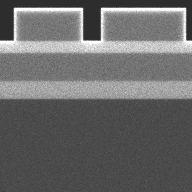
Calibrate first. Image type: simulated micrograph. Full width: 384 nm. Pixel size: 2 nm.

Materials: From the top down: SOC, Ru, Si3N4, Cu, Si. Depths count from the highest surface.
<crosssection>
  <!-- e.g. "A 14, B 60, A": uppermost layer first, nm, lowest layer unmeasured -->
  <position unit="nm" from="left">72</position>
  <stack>SOC 66, Ru 24, Si3N4 56, Cu 36, Si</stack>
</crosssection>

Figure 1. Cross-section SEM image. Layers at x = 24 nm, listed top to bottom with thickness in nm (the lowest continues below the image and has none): empty 66, Ru 24, Si3N4 56, Cu 36, Si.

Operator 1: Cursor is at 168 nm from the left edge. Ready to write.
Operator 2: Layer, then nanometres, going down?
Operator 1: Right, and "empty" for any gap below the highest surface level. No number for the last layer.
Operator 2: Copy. empty 66, Ru 24, Si3N4 56, Cu 36, Si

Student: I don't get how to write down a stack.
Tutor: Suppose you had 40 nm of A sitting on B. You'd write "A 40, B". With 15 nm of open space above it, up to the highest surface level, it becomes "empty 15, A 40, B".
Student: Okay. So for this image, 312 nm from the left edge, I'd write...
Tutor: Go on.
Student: SOC 66, Ru 24, Si3N4 56, Cu 36, Si